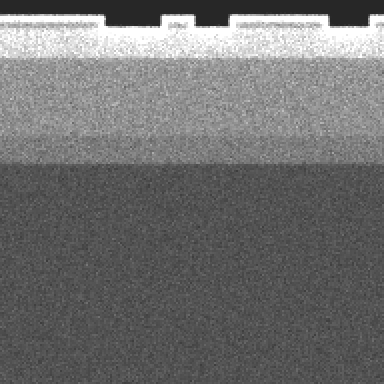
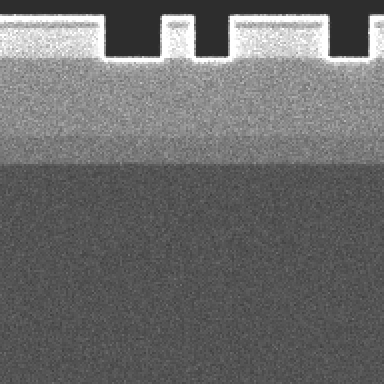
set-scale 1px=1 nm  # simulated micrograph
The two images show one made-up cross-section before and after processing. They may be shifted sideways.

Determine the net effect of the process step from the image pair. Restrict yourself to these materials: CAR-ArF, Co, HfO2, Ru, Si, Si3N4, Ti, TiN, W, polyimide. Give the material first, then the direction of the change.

Co: removed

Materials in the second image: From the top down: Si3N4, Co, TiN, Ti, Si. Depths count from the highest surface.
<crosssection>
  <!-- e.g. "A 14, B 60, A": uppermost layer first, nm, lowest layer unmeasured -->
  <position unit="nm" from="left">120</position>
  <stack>empty 42, TiN 78, Ti 28, Si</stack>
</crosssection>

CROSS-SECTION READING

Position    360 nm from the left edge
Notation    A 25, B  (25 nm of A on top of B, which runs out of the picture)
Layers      empty 42, TiN 78, Ti 28, Si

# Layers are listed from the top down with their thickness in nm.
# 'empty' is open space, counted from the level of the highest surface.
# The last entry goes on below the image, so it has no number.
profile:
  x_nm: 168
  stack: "Si3N4 12, Co 30, TiN 78, Ti 28, Si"